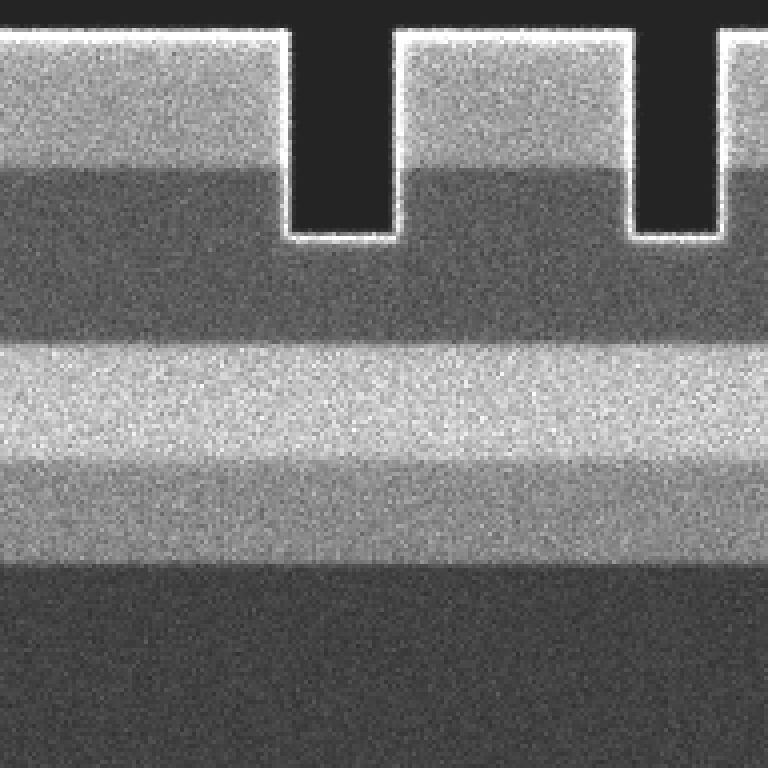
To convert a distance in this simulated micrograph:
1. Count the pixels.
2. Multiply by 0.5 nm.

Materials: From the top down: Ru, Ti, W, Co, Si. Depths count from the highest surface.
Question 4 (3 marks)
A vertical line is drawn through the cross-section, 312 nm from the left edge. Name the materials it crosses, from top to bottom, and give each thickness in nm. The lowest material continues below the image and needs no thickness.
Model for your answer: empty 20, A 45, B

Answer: Ru 68, Ti 88, W 58, Co 52, Si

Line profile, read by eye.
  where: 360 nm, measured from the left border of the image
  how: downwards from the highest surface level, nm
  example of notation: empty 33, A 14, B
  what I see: Ru 68, Ti 88, W 58, Co 52, Si